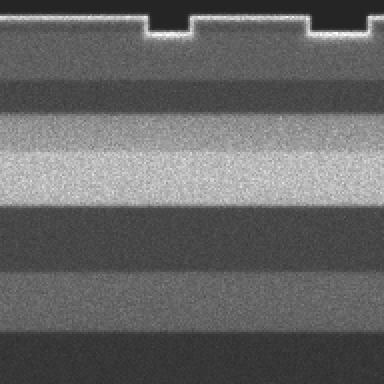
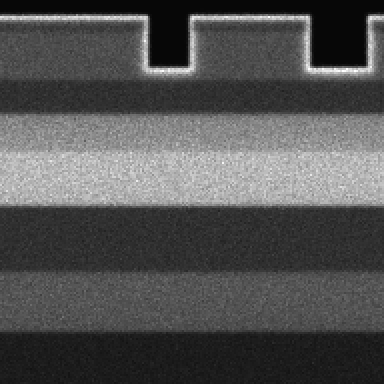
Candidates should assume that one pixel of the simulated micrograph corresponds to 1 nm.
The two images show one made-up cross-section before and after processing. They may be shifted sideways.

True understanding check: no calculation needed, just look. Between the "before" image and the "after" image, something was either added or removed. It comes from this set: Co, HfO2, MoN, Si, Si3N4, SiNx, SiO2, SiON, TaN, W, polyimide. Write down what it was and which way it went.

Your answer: SiO2 (removed)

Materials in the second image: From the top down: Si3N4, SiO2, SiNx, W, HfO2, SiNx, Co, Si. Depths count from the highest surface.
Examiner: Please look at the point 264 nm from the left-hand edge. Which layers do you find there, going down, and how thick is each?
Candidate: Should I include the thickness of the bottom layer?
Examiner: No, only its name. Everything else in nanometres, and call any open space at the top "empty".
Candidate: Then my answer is Si3N4 16, SiO2 48, SiNx 34, W 38, HfO2 54, SiNx 66, Co 60, Si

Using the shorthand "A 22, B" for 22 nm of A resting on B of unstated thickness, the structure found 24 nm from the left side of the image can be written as Si3N4 16, SiO2 48, SiNx 34, W 38, HfO2 54, SiNx 66, Co 60, Si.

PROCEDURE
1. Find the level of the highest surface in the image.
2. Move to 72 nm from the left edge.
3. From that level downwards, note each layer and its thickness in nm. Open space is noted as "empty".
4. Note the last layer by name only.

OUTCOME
Si3N4 16, SiO2 48, SiNx 34, W 38, HfO2 54, SiNx 66, Co 60, Si